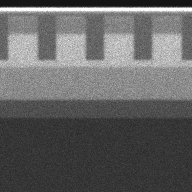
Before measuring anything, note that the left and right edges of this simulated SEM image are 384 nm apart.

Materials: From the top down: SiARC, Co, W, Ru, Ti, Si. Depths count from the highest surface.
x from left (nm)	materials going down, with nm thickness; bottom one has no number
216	SiARC 16, Co 36, W 66, Ru 66, Ti 36, Si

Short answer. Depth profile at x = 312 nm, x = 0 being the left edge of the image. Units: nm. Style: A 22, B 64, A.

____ SiARC 16, Co 36, W 66, Ru 66, Ti 36, Si